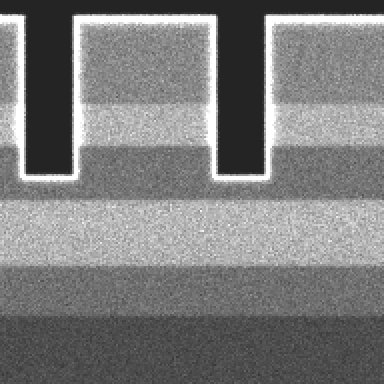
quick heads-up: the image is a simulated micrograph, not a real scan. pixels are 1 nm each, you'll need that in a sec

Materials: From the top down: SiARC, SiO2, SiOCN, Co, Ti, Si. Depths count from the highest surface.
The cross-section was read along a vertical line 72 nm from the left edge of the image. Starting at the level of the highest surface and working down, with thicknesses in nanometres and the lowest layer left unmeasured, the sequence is empty 160, SiOCN 24, Co 66, Ti 50, Si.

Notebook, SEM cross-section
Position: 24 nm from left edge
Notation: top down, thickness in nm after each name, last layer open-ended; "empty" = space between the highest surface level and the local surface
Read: empty 160, SiOCN 24, Co 66, Ti 50, Si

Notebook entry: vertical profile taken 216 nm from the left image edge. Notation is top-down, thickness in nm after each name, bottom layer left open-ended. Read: empty 160, SiOCN 24, Co 66, Ti 50, Si